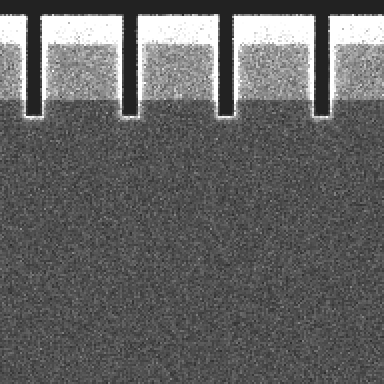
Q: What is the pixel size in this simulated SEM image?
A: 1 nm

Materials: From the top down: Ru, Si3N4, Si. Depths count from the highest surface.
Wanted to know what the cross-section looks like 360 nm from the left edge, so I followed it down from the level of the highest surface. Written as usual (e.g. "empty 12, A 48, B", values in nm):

Ru 28, Si3N4 56, Si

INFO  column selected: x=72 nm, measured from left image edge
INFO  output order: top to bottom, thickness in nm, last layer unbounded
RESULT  Ru 28, Si3N4 56, Si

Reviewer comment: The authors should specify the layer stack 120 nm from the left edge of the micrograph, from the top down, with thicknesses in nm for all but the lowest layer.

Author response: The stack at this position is Ru 28, Si3N4 56, Si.